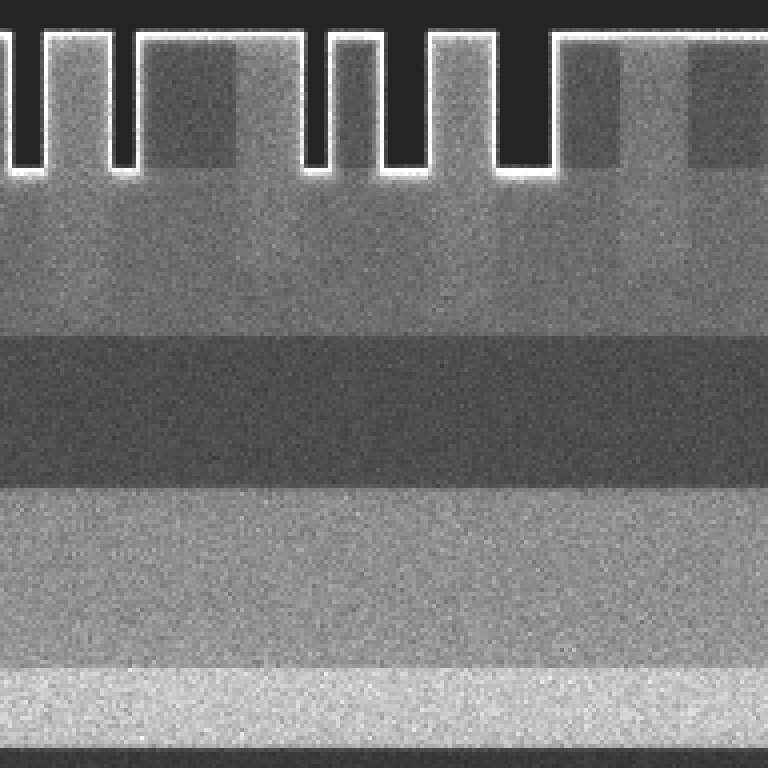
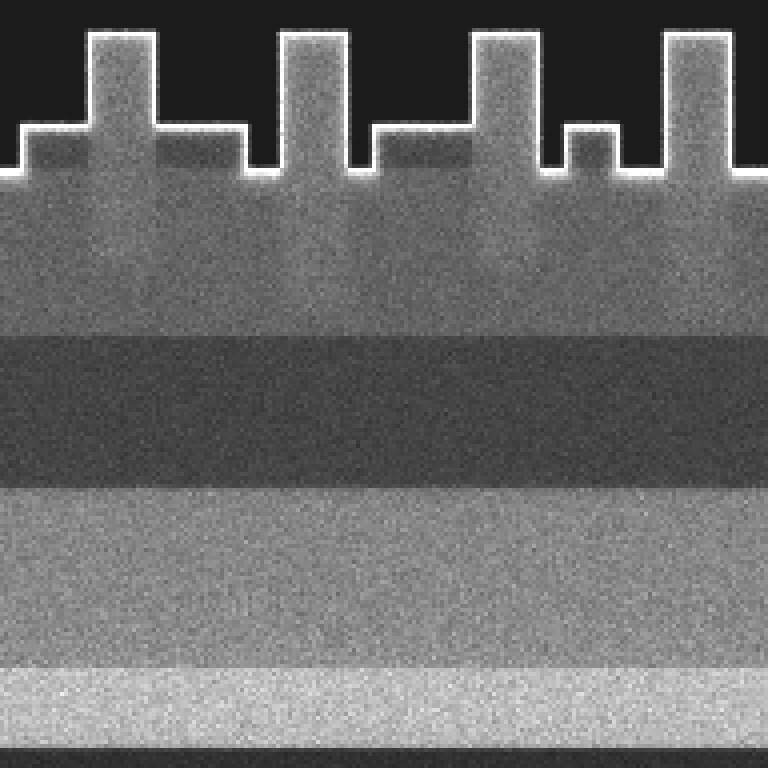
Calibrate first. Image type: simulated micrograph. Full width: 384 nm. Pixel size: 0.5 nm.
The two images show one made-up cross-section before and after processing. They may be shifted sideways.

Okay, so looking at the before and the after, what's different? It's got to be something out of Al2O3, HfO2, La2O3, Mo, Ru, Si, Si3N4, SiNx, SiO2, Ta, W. Si3N4, removed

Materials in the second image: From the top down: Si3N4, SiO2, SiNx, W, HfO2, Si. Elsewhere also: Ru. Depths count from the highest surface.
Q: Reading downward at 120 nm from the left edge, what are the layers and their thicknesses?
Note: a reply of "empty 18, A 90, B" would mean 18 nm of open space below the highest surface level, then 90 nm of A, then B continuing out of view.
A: empty 46, Si3N4 22, SiO2 84, SiNx 76, W 90, HfO2 40, Si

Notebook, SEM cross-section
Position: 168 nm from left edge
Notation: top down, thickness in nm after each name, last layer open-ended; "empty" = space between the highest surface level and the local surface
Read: Ru 144, SiO2 8, SiNx 76, W 90, HfO2 40, Si